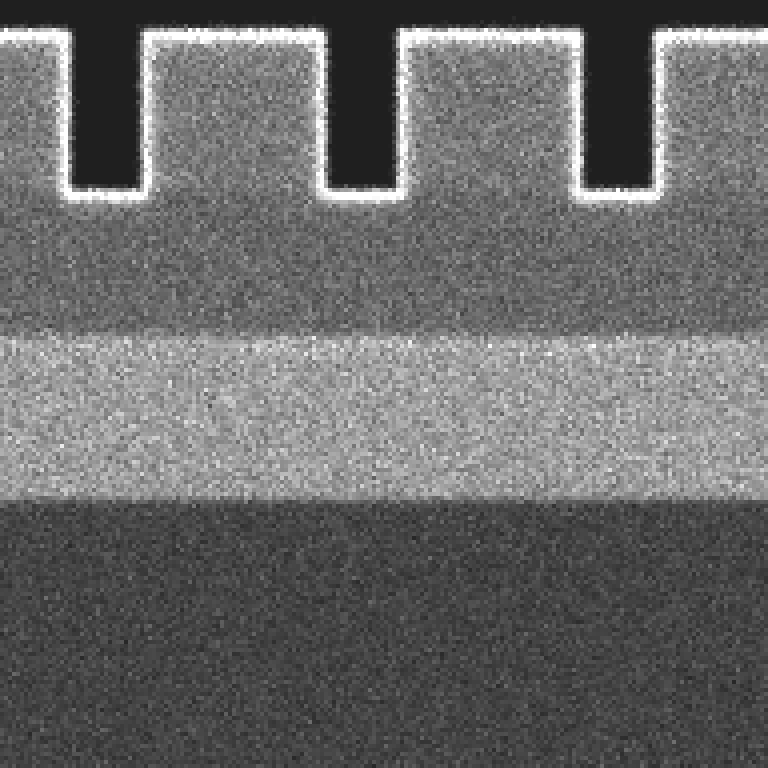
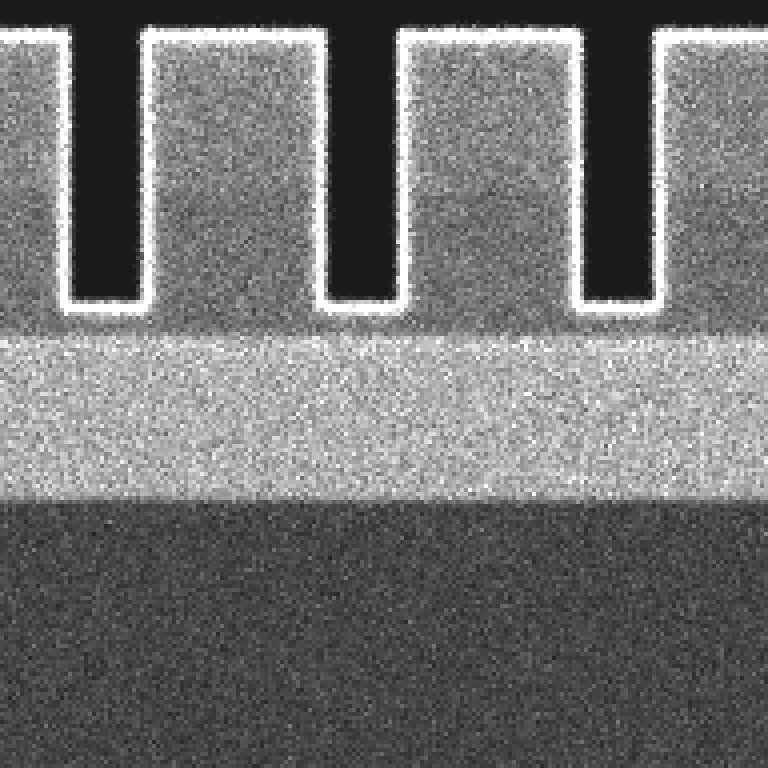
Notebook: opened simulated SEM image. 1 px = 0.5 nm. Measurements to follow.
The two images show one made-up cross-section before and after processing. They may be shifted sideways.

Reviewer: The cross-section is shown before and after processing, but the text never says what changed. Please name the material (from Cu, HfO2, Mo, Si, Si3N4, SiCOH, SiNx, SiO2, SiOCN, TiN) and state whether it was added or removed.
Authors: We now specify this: SiNx, removed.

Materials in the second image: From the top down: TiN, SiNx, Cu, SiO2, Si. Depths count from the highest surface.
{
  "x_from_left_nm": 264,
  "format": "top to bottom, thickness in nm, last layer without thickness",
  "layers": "TiN 80, SiNx 72, Cu 8, SiO2 74, Si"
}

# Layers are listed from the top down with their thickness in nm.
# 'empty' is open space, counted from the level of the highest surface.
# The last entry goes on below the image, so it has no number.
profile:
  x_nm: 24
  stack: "TiN 80, SiNx 72, Cu 8, SiO2 74, Si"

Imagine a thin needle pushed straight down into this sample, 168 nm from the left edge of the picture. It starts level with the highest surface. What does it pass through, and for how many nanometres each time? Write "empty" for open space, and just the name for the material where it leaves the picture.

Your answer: empty 136, SiNx 16, Cu 8, SiO2 74, Si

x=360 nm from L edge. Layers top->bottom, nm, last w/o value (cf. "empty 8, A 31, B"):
TiN 80, SiNx 72, Cu 8, SiO2 74, Si